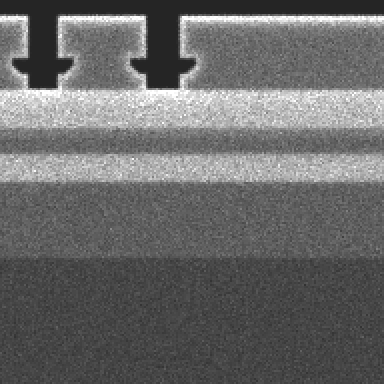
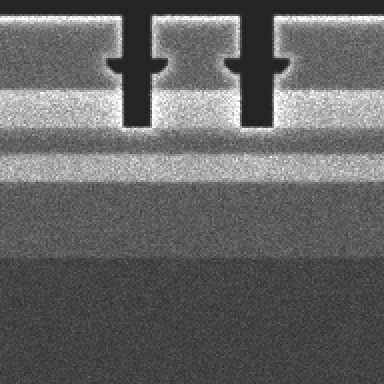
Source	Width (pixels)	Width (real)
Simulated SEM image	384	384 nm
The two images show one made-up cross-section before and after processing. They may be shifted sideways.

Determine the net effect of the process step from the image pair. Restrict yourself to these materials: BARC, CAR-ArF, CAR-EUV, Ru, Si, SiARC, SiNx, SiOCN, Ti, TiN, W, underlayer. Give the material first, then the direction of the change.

W: removed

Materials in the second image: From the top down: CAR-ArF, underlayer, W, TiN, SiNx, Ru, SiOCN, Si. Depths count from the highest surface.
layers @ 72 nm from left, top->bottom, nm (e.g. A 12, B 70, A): CAR-ArF 42, underlayer 32, W 38, TiN 10, SiNx 16, Ru 28, SiOCN 76, Si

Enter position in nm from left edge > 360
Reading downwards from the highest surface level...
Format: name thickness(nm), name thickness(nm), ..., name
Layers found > CAR-ArF 42, underlayer 32, W 38, TiN 10, SiNx 16, Ru 28, SiOCN 76, Si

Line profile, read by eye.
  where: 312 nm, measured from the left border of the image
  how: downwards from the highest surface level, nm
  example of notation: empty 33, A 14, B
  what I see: CAR-ArF 42, underlayer 32, W 38, TiN 10, SiNx 16, Ru 28, SiOCN 76, Si